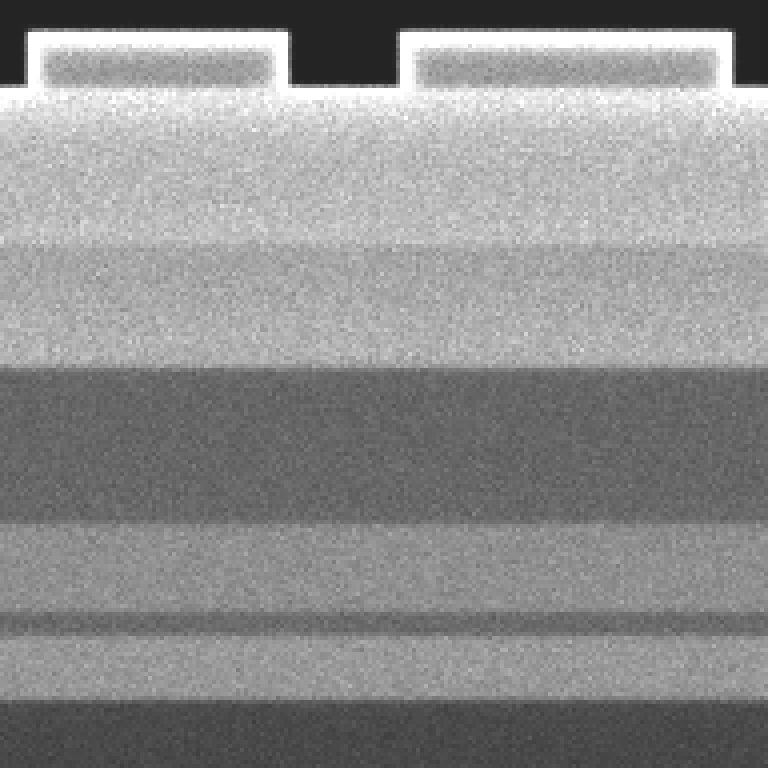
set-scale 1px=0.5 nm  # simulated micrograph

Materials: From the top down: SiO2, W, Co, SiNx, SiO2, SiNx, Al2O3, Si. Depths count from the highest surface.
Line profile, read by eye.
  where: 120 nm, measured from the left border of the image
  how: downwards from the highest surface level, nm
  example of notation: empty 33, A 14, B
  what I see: SiO2 28, W 78, Co 62, SiNx 78, SiO2 44, SiNx 12, Al2O3 32, Si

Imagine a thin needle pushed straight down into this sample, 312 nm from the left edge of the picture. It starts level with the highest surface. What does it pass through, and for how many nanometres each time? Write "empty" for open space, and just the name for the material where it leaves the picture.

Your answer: SiO2 28, W 78, Co 62, SiNx 78, SiO2 44, SiNx 12, Al2O3 32, Si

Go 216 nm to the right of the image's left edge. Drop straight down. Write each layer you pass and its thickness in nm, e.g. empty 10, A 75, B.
SiO2 28, W 78, Co 62, SiNx 78, SiO2 44, SiNx 12, Al2O3 32, Si